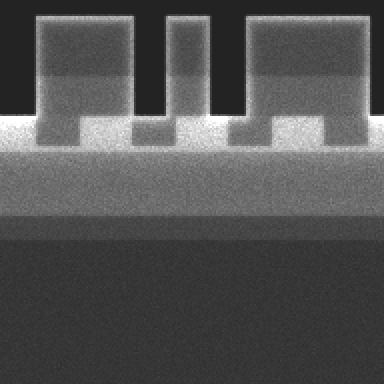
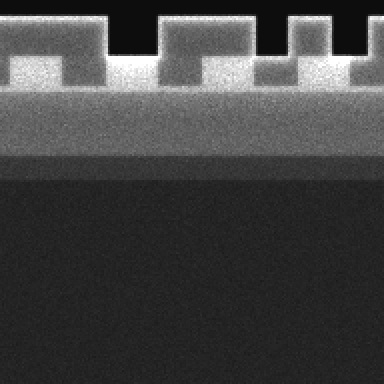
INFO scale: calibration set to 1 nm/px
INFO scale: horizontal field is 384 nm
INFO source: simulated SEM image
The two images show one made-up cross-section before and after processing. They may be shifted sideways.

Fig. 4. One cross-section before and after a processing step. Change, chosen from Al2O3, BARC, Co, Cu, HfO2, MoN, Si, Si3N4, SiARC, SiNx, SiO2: SiARC removed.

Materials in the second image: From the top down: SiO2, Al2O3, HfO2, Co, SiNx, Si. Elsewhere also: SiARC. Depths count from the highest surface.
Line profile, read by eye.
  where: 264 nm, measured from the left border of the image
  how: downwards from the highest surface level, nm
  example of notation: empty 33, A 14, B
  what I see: empty 40, Al2O3 30, HfO2 6, Co 64, SiNx 24, Si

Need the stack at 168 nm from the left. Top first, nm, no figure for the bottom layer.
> SiO2 40, Al2O3 30, HfO2 6, Co 64, SiNx 24, Si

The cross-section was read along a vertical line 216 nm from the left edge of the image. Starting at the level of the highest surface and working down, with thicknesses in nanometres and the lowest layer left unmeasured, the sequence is SiO2 40, HfO2 36, Co 64, SiNx 24, Si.